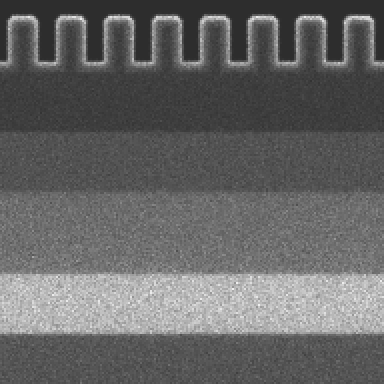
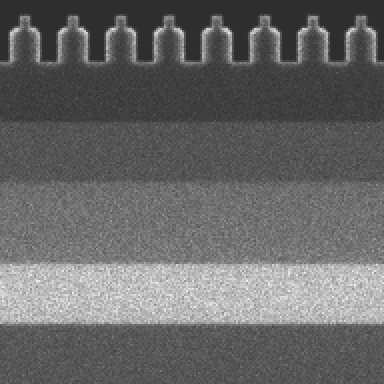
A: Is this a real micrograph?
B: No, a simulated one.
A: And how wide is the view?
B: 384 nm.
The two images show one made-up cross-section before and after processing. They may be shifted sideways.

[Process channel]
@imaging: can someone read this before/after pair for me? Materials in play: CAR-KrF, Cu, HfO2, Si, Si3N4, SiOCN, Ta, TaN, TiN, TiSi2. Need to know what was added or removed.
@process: SiOCN removed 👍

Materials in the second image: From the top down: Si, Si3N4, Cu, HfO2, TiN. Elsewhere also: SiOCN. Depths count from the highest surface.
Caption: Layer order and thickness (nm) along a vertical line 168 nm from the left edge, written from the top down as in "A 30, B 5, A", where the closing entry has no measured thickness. Si 106, Si3N4 60, Cu 82, HfO2 60, TiN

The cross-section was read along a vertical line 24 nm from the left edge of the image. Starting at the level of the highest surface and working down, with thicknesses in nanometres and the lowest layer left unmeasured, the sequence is Si 106, Si3N4 60, Cu 82, HfO2 60, TiN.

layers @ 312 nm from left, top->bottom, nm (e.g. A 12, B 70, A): Si 106, Si3N4 60, Cu 82, HfO2 60, TiN